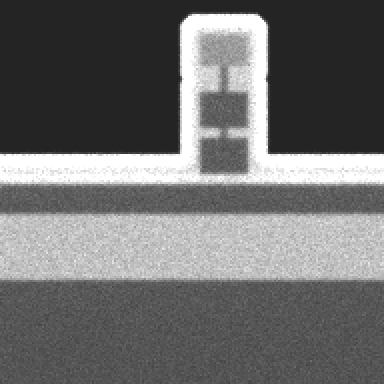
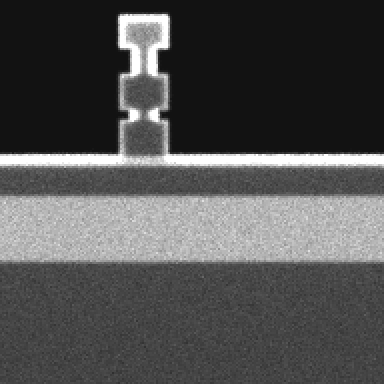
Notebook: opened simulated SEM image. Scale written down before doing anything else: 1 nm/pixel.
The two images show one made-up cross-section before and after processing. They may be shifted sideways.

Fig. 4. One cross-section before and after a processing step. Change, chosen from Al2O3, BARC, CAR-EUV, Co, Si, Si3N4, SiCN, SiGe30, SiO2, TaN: Al2O3 removed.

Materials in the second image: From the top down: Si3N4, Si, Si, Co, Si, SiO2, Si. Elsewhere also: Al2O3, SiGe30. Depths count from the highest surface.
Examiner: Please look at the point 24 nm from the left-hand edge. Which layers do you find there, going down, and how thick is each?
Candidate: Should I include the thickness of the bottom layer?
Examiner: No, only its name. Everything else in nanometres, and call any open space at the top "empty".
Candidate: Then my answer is empty 140, Co 10, Si 30, SiO2 66, Si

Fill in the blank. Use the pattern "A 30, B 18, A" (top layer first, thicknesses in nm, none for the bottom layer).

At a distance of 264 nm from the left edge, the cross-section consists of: empty 140, Co 10, Si 30, SiO2 66, Si